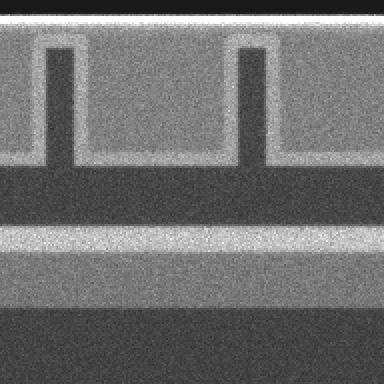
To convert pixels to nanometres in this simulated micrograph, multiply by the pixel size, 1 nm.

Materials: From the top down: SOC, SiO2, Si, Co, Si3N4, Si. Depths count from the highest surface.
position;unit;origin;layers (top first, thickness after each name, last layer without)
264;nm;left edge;SOC 18, SiO2 14, Si 178, Co 26, Si3N4 56, Si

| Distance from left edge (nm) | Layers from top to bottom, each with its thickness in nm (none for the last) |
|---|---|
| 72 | SOC 18, SiO2 14, Si 178, Co 26, Si3N4 56, Si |